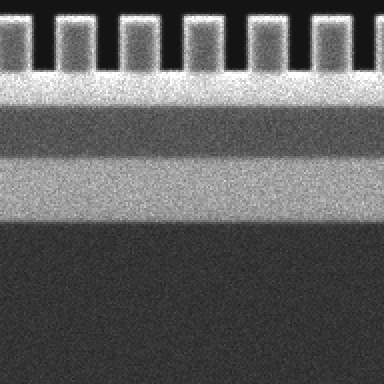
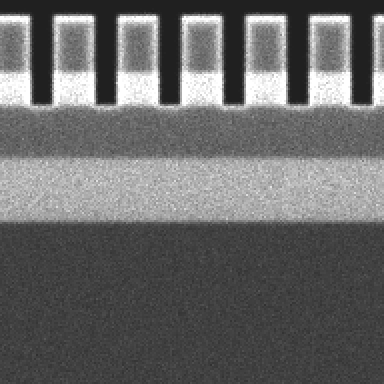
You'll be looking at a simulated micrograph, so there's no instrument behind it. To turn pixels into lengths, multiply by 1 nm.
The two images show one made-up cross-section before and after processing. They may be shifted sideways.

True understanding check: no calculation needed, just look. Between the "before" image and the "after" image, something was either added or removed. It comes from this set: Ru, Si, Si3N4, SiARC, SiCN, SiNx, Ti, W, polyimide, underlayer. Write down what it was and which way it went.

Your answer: W (removed)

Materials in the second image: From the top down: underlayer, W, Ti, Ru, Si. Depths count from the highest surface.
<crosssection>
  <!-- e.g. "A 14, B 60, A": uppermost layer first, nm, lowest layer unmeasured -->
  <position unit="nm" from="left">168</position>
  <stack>empty 90, Ti 52, Ru 64, Si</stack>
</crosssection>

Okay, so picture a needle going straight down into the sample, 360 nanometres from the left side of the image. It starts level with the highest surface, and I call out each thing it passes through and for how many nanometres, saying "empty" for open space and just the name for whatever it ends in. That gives empty 90, Ti 52, Ru 64, Si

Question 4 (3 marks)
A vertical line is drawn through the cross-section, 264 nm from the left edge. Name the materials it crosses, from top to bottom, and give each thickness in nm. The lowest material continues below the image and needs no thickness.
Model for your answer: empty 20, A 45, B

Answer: underlayer 56, W 34, Ti 52, Ru 64, Si